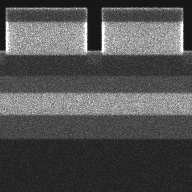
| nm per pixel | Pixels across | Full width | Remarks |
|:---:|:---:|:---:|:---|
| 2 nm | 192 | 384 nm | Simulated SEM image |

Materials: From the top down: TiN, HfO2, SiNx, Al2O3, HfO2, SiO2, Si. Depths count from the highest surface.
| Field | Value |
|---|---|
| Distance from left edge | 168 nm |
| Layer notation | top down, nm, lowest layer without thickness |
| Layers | TiN 28, HfO2 66, SiNx 42, Al2O3 34, HfO2 44, SiO2 48, Si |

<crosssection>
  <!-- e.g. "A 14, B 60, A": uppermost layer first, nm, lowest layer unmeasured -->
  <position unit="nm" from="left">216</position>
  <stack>TiN 28, HfO2 66, SiNx 42, Al2O3 34, HfO2 44, SiO2 48, Si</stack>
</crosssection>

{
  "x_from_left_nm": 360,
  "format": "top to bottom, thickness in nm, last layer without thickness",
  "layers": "TiN 28, HfO2 66, SiNx 42, Al2O3 34, HfO2 44, SiO2 48, Si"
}